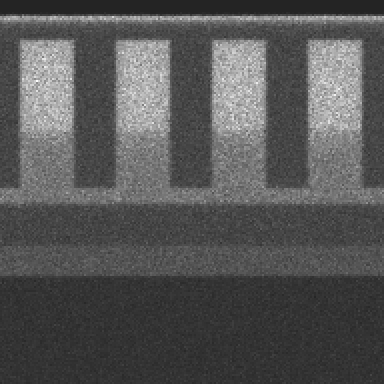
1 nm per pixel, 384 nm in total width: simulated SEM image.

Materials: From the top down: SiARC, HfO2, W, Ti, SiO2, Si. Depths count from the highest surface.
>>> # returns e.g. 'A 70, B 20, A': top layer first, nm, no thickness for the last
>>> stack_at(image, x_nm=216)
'SiARC 24, HfO2 90, W 74, Ti 42, SiO2 30, Si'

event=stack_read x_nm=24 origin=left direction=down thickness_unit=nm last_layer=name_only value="SiARC 24, HfO2 90, W 74, Ti 42, SiO2 30, Si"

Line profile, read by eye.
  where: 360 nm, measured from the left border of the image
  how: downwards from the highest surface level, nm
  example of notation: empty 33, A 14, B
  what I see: SiARC 24, HfO2 90, W 74, Ti 42, SiO2 30, Si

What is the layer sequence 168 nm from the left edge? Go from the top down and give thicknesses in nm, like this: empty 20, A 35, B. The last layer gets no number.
SiARC 24, HfO2 90, W 74, Ti 42, SiO2 30, Si